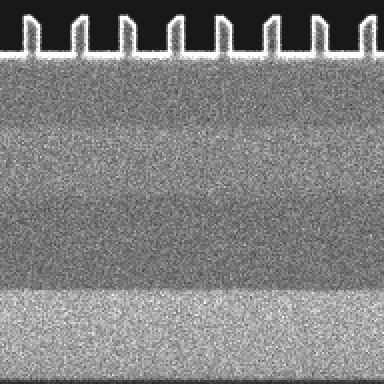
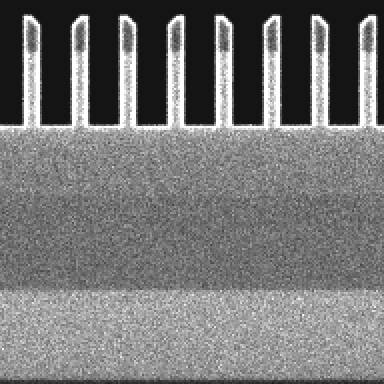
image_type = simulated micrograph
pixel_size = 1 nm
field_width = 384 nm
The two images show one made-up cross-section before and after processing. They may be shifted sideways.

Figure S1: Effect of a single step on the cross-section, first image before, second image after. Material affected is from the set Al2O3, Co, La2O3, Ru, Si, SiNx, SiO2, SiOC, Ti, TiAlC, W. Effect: removed Al2O3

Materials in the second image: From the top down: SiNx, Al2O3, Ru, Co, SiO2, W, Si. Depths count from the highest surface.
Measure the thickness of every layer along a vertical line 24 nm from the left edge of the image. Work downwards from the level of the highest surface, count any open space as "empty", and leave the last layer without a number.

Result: SiNx 36, Al2O3 74, Ru 70, Co 52, SiO2 42, W 90, Si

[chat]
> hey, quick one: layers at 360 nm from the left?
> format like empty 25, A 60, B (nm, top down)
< empty 8, SiNx 28, Al2O3 74, Ru 70, Co 52, SiO2 42, W 90, Si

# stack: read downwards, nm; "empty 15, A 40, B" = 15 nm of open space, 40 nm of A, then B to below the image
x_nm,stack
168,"empty 8, SiNx 28, Al2O3 74, Ru 70, Co 52, SiO2 42, W 90, Si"